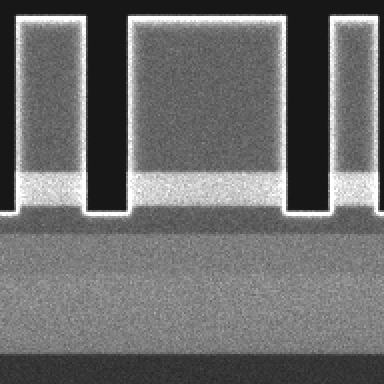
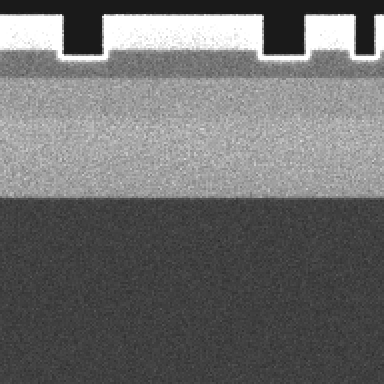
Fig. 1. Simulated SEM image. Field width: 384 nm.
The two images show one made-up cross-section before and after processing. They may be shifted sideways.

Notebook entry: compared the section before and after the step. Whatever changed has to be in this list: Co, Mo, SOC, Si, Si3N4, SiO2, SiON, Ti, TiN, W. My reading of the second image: SOC removed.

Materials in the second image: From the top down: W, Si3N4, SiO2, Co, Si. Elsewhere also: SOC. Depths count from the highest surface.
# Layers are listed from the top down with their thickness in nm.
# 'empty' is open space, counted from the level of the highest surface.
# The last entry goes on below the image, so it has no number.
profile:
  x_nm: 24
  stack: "W 34, Si3N4 28, SiO2 40, Co 80, Si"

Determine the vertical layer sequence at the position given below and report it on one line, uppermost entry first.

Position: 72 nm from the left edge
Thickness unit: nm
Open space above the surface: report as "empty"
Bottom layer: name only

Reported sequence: empty 40, Si3N4 22, SiO2 40, Co 80, Si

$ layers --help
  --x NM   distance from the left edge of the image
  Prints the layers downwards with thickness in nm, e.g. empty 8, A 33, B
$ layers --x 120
W 34, Si3N4 28, SiO2 40, Co 80, Si